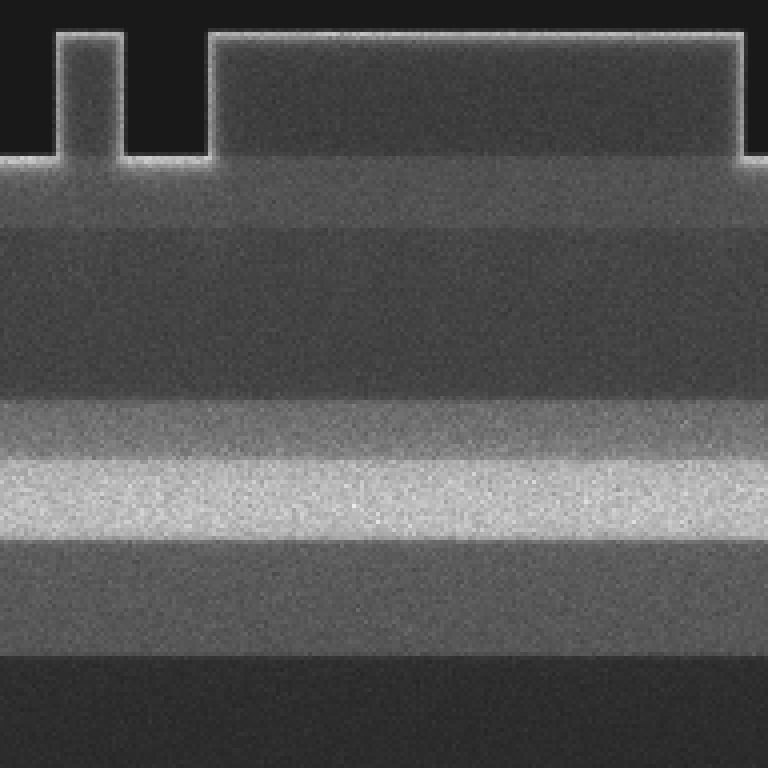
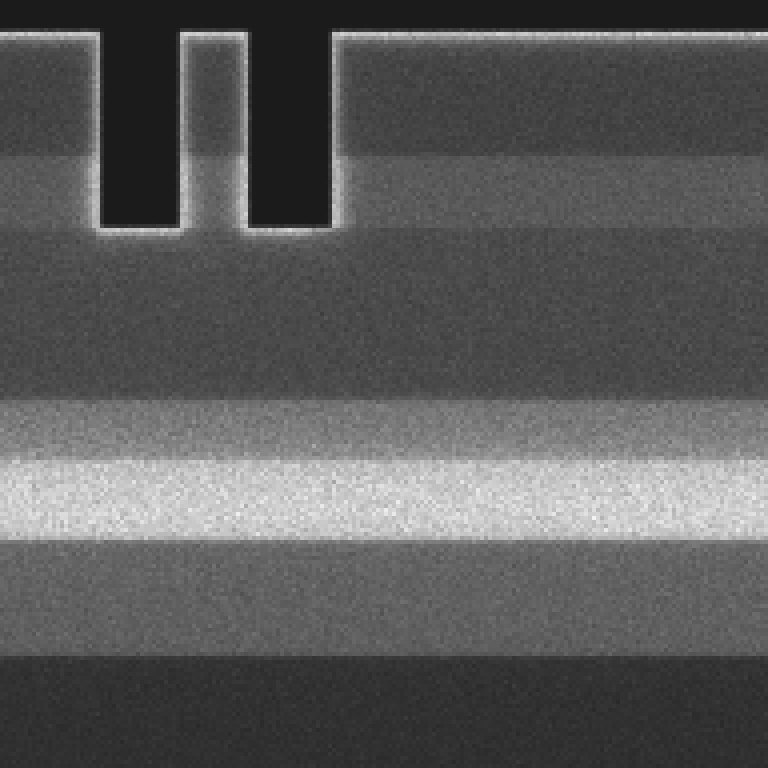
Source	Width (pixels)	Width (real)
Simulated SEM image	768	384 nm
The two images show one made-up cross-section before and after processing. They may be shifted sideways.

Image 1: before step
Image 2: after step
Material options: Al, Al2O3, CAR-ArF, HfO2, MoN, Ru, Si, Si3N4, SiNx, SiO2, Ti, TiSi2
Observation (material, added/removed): SiO2, removed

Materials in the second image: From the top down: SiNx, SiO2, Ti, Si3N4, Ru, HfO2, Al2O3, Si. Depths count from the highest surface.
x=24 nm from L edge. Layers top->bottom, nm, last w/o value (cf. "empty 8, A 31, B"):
SiNx 62, SiO2 36, Si3N4 86, Ru 30, HfO2 40, Al2O3 58, Si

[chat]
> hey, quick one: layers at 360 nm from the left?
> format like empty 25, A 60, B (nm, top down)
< SiNx 62, SiO2 36, Ti 22, Si3N4 64, Ru 30, HfO2 40, Al2O3 58, Si